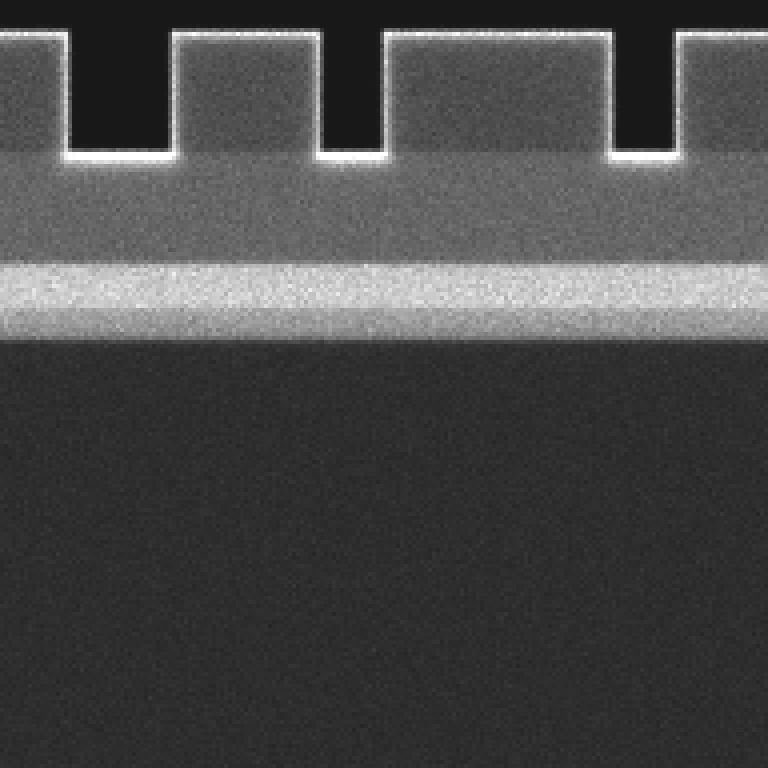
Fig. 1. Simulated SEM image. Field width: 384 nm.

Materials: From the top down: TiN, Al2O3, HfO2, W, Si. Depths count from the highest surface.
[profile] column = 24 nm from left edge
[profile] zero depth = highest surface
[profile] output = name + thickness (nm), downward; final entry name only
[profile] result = TiN 60, Al2O3 56, HfO2 22, W 16, Si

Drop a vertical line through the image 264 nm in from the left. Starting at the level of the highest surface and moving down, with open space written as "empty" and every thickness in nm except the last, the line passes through TiN 60, Al2O3 56, HfO2 22, W 16, Si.